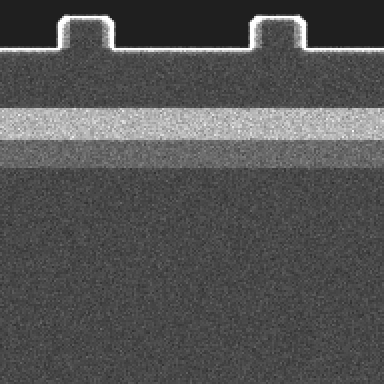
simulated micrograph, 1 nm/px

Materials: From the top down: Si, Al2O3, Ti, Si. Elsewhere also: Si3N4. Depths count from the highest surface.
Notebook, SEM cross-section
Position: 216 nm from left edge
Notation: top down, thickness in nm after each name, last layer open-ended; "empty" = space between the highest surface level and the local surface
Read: empty 32, Si 60, Al2O3 32, Ti 28, Si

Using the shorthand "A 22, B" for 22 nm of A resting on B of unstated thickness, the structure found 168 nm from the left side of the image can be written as empty 32, Si 60, Al2O3 32, Ti 28, Si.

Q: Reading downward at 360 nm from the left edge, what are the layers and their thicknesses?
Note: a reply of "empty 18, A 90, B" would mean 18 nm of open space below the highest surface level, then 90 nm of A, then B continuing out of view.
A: empty 32, Si 60, Al2O3 32, Ti 28, Si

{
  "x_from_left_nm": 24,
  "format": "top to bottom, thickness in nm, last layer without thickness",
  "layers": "empty 32, Si 60, Al2O3 32, Ti 28, Si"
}